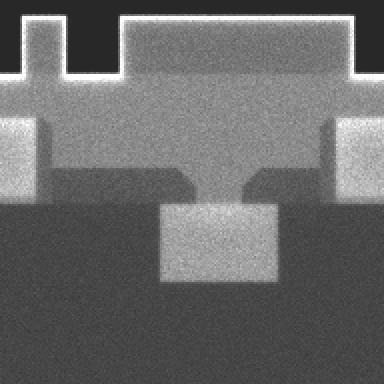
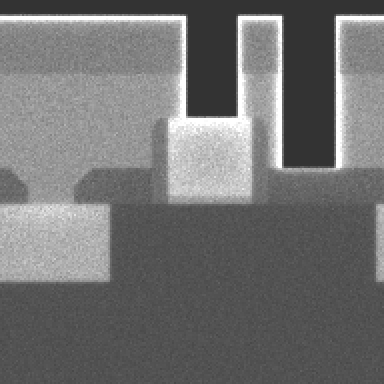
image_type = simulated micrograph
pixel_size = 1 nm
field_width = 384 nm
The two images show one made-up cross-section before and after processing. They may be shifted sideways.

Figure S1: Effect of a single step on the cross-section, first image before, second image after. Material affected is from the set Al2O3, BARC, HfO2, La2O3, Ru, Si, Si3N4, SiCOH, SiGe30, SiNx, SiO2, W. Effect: removed SiO2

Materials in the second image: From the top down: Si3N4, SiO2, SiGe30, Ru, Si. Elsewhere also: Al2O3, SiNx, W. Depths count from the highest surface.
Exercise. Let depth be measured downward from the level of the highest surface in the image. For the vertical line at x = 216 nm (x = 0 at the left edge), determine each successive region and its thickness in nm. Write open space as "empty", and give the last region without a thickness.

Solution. empty 102, W 78, Al2O3 8, Si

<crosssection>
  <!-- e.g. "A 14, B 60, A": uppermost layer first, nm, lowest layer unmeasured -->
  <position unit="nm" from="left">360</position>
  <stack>Si3N4 58, SiO2 94, SiGe30 36, Si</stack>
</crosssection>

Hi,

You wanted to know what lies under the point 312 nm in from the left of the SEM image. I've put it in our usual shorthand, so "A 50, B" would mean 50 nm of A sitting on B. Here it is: empty 152, SiGe30 36, Si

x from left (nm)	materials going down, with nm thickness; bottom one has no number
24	Si3N4 58, SiO2 110, SiGe30 20, Ru 78, Si